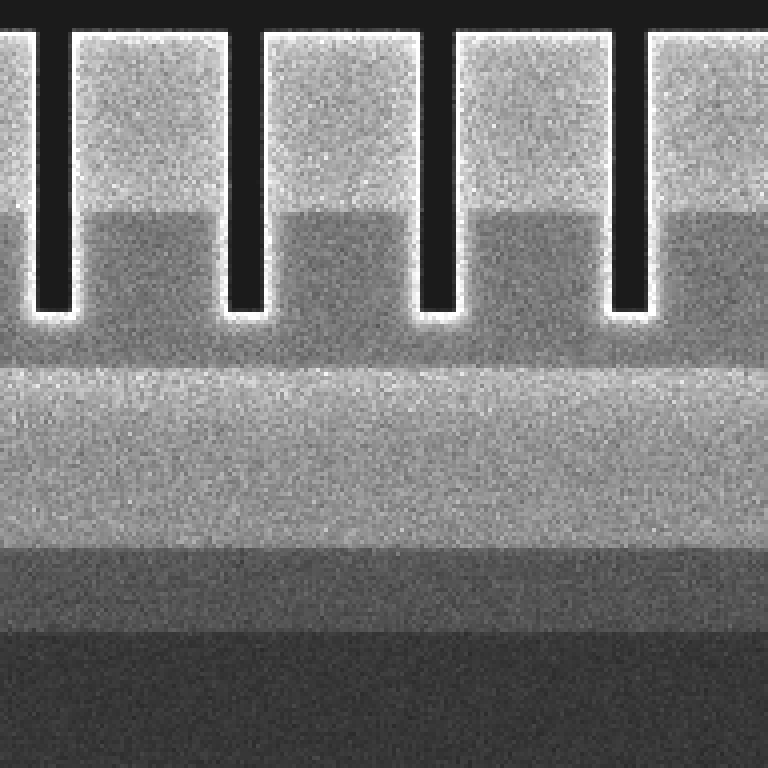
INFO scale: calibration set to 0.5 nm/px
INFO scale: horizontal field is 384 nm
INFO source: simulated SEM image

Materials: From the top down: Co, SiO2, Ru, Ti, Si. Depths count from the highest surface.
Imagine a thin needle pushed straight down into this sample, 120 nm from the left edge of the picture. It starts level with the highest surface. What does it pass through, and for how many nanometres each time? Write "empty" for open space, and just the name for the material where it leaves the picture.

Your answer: empty 140, SiO2 28, Ru 90, Ti 42, Si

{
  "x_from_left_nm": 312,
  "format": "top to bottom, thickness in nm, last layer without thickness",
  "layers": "empty 140, SiO2 28, Ru 90, Ti 42, Si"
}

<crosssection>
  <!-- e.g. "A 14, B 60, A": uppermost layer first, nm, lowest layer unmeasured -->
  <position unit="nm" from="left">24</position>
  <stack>empty 140, SiO2 28, Ru 90, Ti 42, Si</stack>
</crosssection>